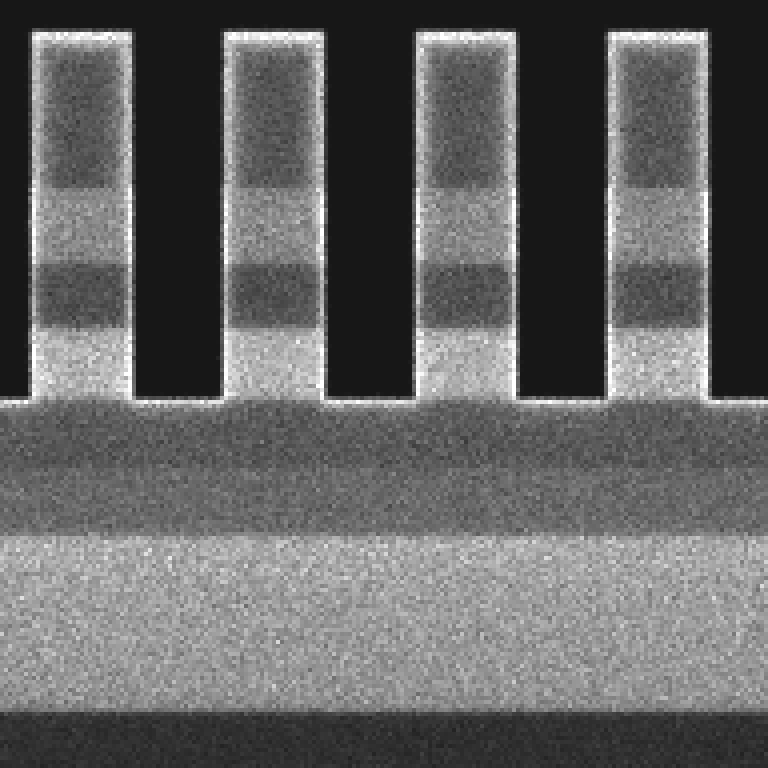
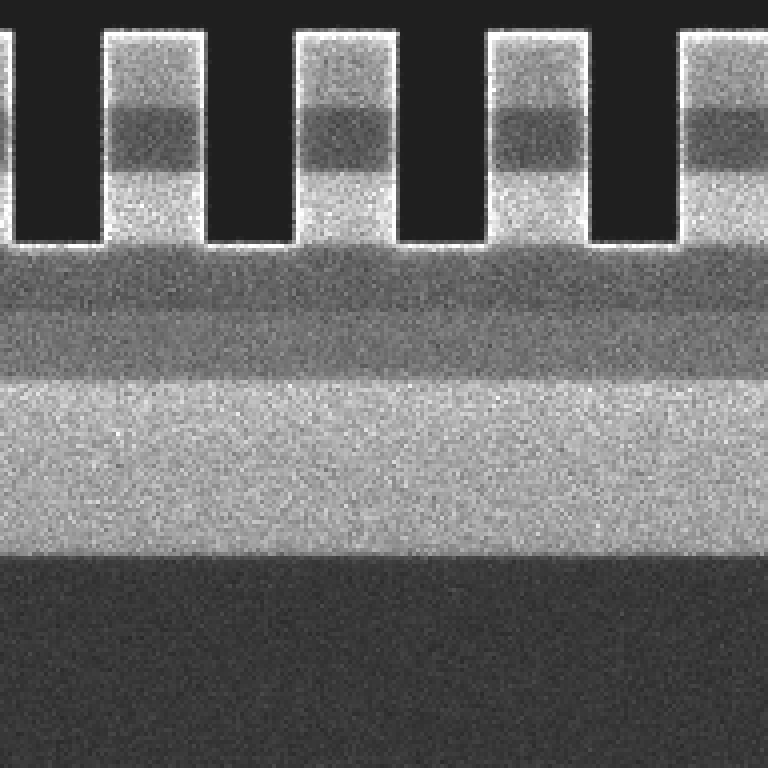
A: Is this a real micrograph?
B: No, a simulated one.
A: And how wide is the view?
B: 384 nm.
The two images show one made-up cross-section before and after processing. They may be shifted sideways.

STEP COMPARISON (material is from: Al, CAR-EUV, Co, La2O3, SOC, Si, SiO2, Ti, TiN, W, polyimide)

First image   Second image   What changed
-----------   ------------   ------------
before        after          SOC, removed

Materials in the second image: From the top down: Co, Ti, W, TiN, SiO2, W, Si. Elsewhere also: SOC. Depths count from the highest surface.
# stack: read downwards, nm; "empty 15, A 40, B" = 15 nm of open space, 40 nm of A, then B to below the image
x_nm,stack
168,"Co 38, Ti 32, W 36, TiN 34, SiO2 34, W 88, Si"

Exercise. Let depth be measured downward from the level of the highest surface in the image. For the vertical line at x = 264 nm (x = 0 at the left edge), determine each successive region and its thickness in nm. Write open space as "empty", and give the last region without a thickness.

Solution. Co 38, Ti 32, W 36, TiN 34, SiO2 34, W 88, Si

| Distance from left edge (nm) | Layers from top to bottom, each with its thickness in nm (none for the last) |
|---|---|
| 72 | Co 38, Ti 32, W 36, TiN 34, SiO2 34, W 88, Si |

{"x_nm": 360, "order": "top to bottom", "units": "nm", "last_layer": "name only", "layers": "Co 38, Ti 32, W 36, TiN 34, SiO2 34, W 88, Si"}